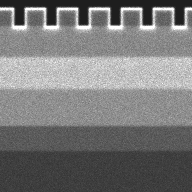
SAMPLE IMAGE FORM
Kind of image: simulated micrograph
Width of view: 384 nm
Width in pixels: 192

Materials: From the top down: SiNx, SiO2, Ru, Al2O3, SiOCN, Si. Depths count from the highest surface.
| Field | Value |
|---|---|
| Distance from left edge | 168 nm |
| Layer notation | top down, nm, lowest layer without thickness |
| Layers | empty 36, SiO2 62, Ru 64, Al2O3 74, SiOCN 50, Si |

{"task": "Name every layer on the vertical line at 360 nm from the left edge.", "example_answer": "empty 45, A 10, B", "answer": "empty 36, SiO2 62, Ru 64, Al2O3 74, SiOCN 50, Si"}